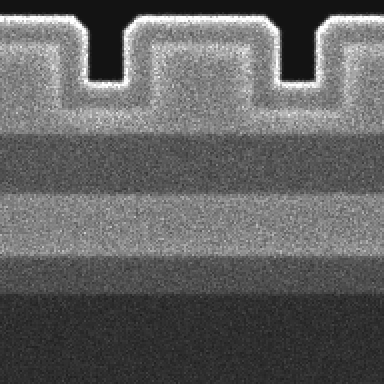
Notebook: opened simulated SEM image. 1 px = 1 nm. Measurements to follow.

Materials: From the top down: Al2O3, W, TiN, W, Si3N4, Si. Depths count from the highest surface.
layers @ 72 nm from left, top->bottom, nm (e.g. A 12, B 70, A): Al2O3 94, W 24, TiN 60, W 62, Si3N4 38, Si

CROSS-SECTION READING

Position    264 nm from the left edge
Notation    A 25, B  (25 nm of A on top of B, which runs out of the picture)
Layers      Al2O3 94, W 24, TiN 60, W 62, Si3N4 38, Si